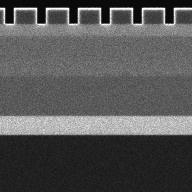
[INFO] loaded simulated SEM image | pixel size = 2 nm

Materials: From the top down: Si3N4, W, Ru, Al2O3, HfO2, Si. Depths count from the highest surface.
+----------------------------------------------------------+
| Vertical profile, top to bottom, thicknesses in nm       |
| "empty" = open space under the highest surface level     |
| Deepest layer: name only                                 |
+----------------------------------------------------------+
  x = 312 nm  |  Si3N4 32, W 24, Ru 80, Al2O3 80, HfO2 38, Si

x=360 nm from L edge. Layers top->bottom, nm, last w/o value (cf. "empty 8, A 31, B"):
Si3N4 32, W 24, Ru 80, Al2O3 80, HfO2 38, Si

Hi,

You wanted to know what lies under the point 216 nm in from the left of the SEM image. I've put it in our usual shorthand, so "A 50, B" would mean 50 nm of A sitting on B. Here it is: empty 32, W 24, Ru 80, Al2O3 80, HfO2 38, Si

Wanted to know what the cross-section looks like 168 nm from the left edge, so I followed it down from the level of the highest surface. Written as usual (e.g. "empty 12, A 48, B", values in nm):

Si3N4 32, W 24, Ru 80, Al2O3 80, HfO2 38, Si